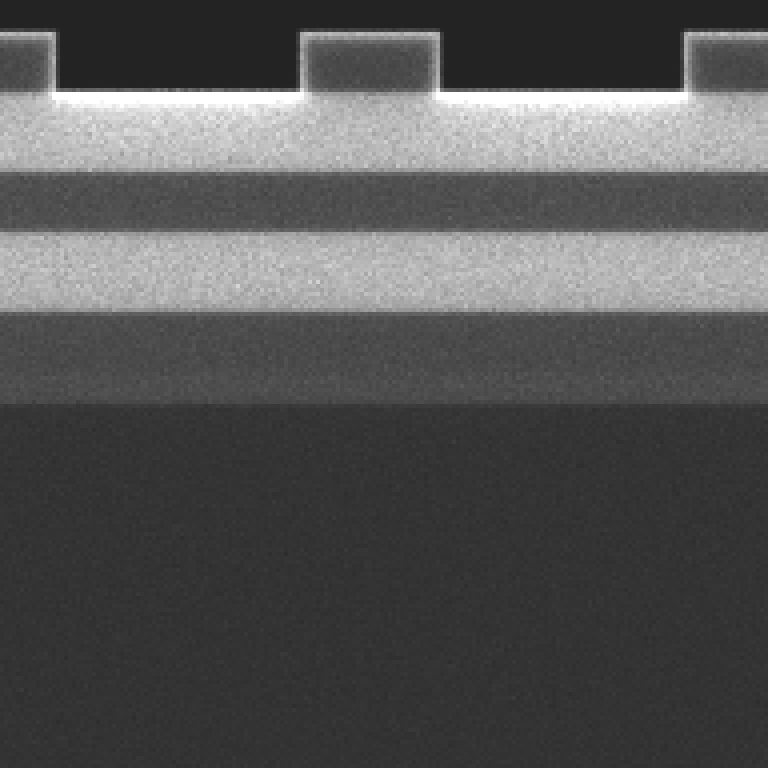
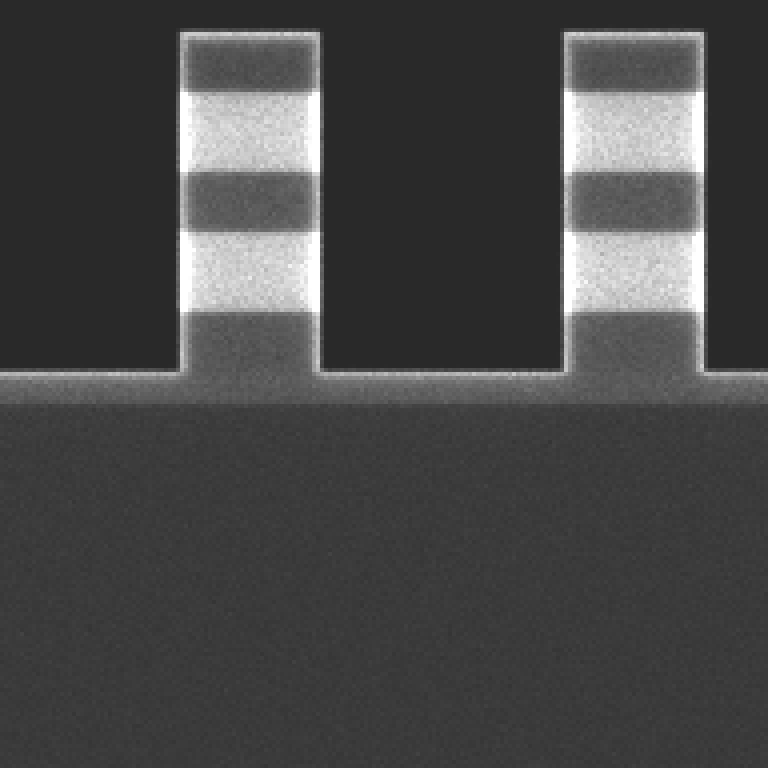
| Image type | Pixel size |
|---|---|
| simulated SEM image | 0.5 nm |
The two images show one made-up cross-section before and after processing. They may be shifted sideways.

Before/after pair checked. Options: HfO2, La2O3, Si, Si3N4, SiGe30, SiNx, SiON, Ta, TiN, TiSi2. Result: removed HfO2 and Si3N4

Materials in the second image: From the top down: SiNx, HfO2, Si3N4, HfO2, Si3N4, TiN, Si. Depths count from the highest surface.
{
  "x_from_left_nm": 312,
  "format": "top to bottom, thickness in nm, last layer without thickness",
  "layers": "SiNx 30, HfO2 40, Si3N4 30, HfO2 40, Si3N4 30, TiN 16, Si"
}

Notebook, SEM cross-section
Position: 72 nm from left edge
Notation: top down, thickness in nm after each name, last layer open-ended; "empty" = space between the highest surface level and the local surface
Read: empty 170, TiN 16, Si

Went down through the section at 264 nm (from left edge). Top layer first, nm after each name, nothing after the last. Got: empty 170, TiN 16, Si